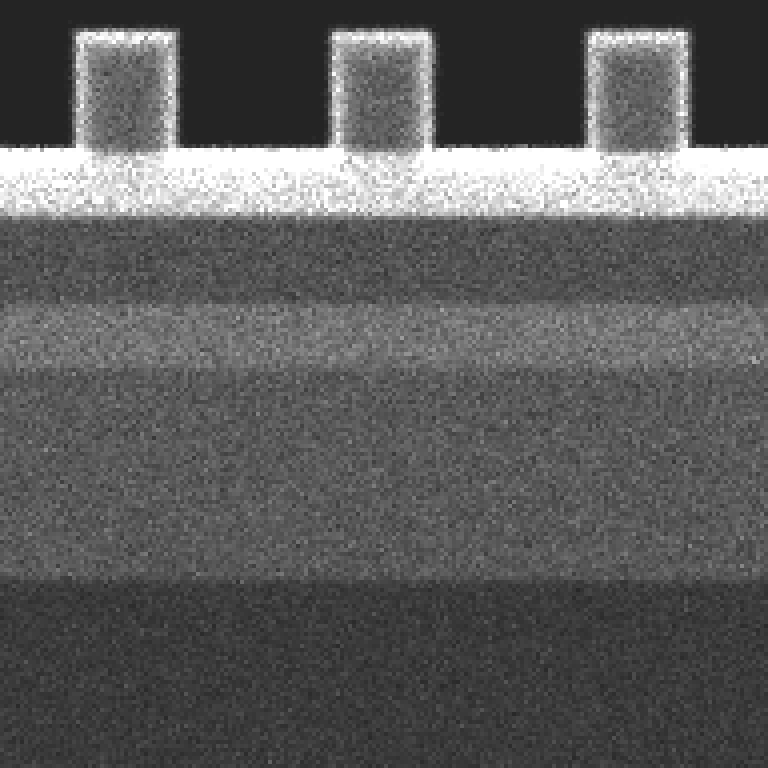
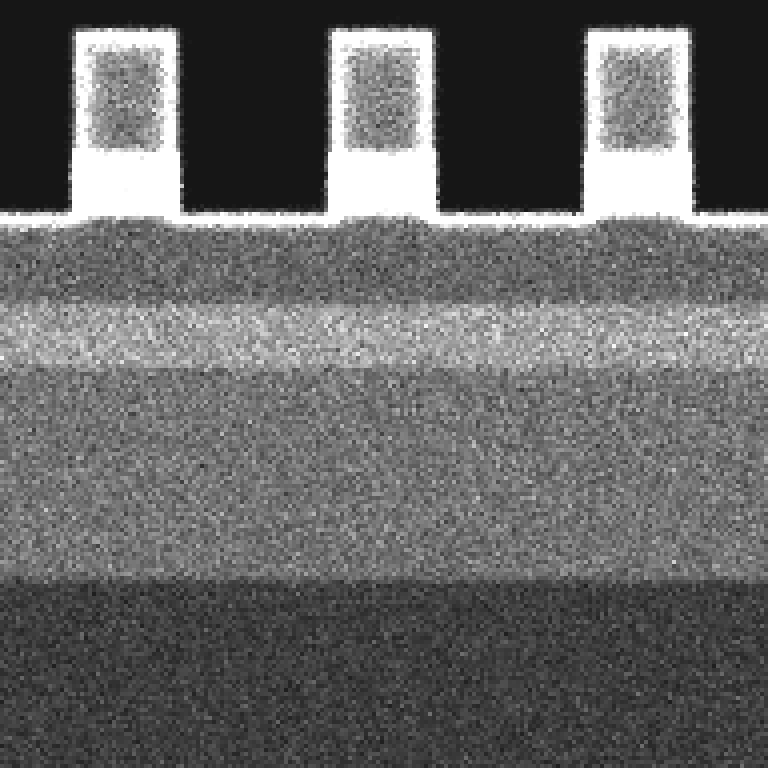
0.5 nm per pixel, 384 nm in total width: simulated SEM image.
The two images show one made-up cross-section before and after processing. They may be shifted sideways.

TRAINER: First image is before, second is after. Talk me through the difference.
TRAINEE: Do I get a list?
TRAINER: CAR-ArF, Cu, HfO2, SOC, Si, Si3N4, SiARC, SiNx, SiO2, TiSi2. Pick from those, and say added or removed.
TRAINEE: removed: HfO2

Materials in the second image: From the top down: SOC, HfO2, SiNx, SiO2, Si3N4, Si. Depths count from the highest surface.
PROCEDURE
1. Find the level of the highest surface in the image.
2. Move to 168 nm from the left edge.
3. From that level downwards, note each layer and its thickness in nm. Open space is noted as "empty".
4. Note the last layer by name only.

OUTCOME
SOC 60, HfO2 32, SiNx 44, SiO2 32, Si3N4 106, Si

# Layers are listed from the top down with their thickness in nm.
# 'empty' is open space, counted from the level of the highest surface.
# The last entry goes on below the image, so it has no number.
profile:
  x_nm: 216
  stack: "empty 92, SiNx 44, SiO2 32, Si3N4 106, Si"